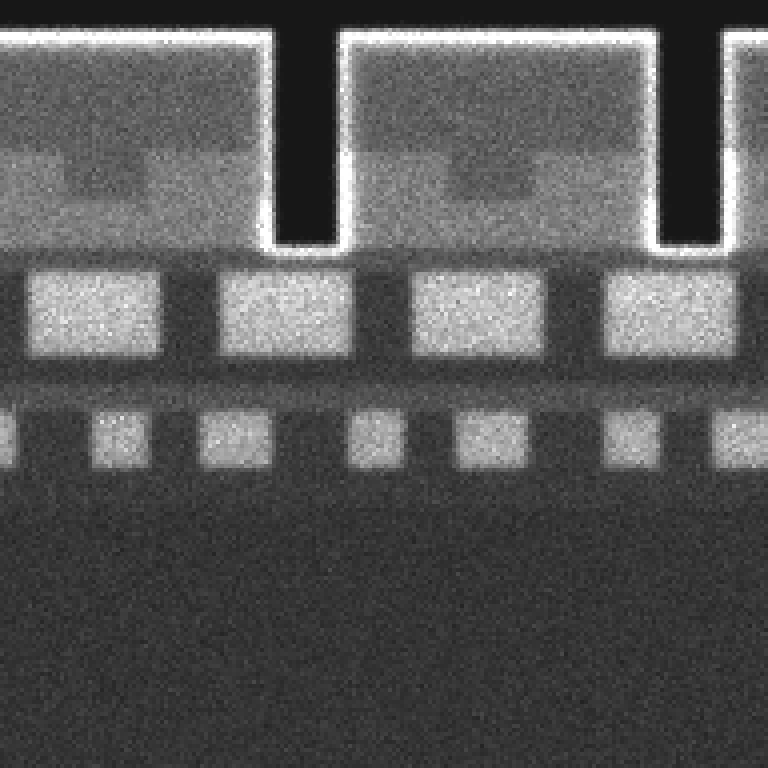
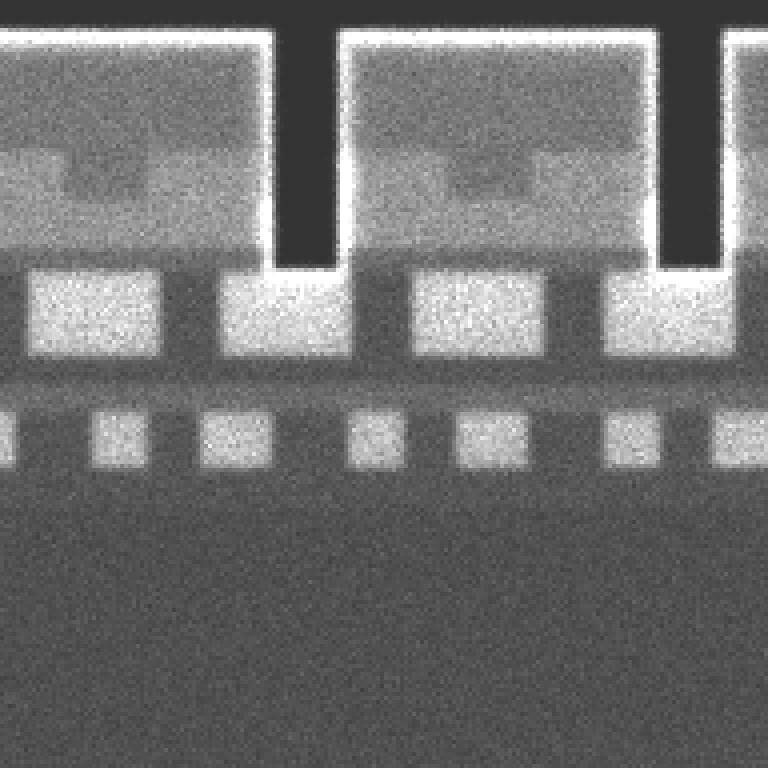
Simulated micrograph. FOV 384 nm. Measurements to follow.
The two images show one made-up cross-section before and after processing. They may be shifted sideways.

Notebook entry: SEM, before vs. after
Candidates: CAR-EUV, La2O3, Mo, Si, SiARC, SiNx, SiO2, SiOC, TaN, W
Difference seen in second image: SiNx removed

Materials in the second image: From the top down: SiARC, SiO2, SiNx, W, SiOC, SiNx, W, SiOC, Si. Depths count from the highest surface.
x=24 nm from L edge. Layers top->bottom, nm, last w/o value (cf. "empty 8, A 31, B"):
SiARC 60, SiO2 48, SiNx 12, W 42, SiOC 14, SiNx 14, SiOC 48, Si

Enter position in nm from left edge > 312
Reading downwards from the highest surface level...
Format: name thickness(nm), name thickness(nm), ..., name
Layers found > SiARC 60, SiO2 48, SiNx 12, W 42, SiOC 14, SiNx 14, W 28, SiOC 20, Si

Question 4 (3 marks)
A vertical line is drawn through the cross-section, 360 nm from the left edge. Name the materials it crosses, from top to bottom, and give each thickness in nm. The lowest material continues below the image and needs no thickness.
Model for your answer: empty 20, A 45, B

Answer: empty 120, W 42, SiOC 14, SiNx 14, W 28, SiOC 20, Si